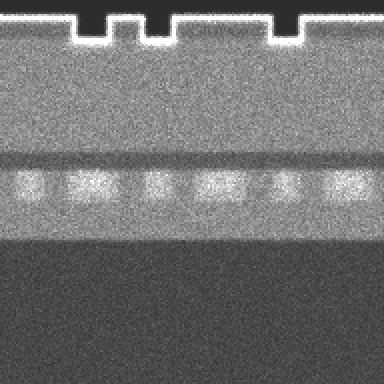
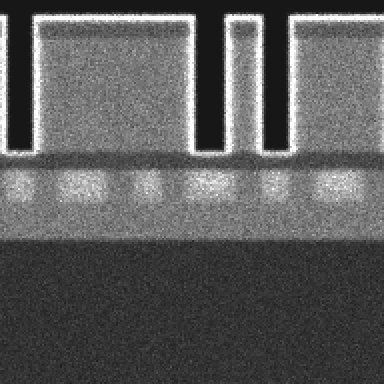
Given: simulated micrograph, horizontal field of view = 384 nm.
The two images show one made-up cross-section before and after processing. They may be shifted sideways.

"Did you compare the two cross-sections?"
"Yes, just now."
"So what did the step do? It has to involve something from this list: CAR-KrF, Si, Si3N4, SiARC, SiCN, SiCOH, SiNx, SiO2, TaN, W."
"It removed SiO2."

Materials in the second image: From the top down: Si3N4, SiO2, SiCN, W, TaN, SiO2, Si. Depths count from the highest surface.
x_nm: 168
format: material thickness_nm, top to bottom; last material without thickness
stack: Si3N4 22, SiO2 114, SiCN 18, SiO2 70, Si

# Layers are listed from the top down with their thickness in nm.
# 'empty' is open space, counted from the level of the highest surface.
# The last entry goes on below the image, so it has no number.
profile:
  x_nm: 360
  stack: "Si3N4 22, SiO2 114, SiCN 18, TaN 32, SiO2 38, Si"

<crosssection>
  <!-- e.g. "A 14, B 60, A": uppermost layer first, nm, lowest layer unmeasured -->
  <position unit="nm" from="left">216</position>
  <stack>empty 136, SiCN 18, W 22, TaN 10, SiO2 38, Si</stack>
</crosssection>